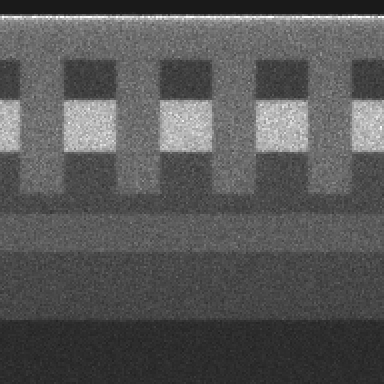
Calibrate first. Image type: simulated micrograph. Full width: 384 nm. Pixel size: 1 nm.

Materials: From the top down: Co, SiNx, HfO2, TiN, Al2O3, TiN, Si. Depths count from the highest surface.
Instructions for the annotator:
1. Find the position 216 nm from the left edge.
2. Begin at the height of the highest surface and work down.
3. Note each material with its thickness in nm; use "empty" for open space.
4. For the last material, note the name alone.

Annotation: Co 178, TiN 20, Al2O3 38, TiN 68, Si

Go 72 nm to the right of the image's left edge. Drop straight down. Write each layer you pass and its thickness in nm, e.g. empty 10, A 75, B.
Co 44, SiNx 40, HfO2 52, TiN 62, Al2O3 38, TiN 68, Si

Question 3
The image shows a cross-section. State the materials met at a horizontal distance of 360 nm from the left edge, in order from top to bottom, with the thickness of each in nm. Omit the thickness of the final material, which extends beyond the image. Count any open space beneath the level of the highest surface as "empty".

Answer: Co 44, SiNx 40, HfO2 52, TiN 62, Al2O3 38, TiN 68, Si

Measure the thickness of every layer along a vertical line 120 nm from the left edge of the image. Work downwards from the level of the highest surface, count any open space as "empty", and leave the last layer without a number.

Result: Co 178, TiN 20, Al2O3 38, TiN 68, Si